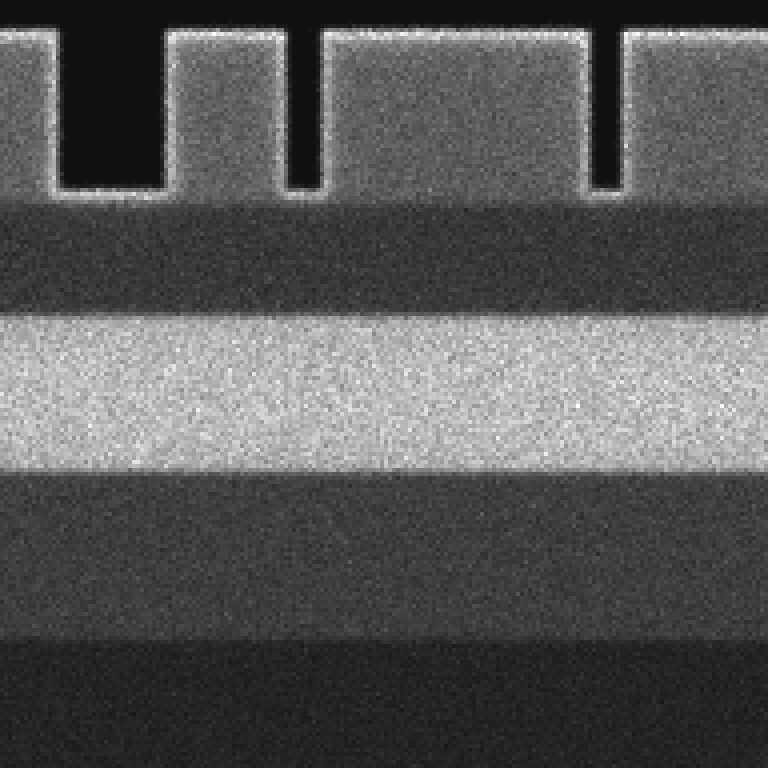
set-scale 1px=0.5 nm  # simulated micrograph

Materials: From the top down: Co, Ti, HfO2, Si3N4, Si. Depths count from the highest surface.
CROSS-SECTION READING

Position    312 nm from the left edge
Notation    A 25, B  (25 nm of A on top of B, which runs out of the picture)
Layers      Co 86, Ti 56, HfO2 78, Si3N4 84, Si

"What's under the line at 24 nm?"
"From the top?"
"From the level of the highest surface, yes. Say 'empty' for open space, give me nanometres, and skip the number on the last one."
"Co 86, Ti 56, HfO2 78, Si3N4 84, Si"